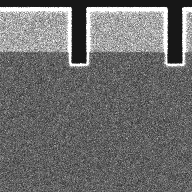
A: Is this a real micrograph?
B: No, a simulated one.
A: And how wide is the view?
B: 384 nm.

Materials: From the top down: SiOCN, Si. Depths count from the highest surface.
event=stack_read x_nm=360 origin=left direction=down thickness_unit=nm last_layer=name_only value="empty 112, Si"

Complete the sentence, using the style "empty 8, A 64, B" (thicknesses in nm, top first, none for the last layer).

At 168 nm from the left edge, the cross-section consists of empty 112, Si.